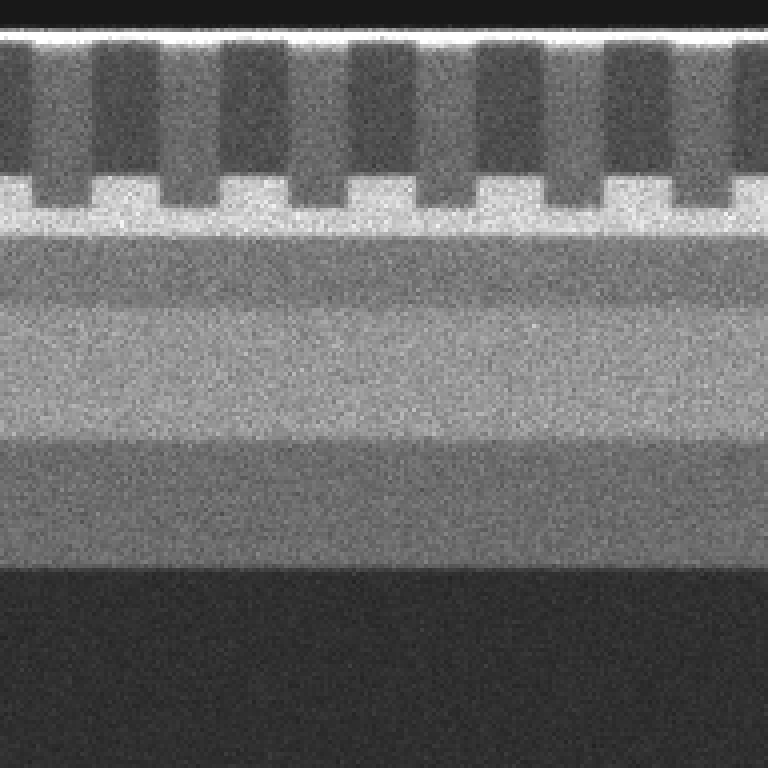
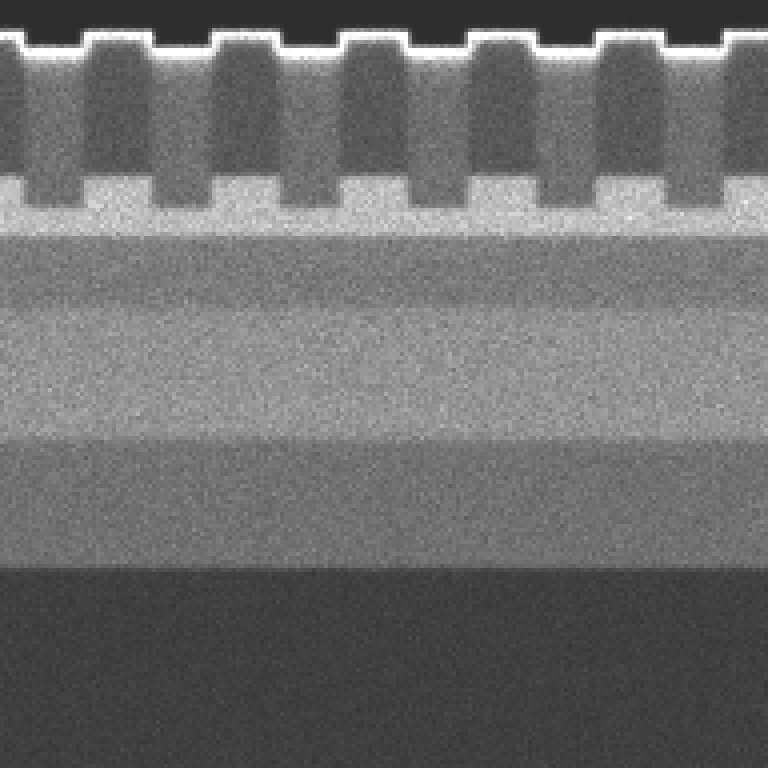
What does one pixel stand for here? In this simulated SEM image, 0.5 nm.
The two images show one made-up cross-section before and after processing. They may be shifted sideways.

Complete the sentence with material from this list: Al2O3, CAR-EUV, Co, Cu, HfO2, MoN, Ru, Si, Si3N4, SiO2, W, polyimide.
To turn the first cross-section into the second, SiO2 must be removed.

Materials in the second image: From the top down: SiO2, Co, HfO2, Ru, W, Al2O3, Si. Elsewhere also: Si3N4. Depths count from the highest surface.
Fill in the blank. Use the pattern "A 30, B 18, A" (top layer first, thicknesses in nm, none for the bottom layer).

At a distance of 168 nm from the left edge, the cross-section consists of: empty 8, SiO2 10, Co 70, HfO2 14, Ru 36, W 66, Al2O3 64, Si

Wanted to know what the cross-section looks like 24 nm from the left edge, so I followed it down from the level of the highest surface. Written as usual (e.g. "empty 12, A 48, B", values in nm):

empty 8, SiO2 10, Co 70, HfO2 14, Ru 36, W 66, Al2O3 64, Si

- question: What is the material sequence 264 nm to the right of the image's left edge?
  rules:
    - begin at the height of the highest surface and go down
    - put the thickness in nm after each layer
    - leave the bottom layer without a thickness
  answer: Si3N4 72, HfO2 30, Ru 36, W 66, Al2O3 64, Si